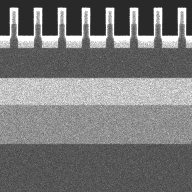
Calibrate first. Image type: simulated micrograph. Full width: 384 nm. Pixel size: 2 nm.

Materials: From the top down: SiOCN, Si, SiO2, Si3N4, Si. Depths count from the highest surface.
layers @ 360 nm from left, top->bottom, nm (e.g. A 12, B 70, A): SiOCN 32, Si 108, SiO2 54, Si3N4 78, Si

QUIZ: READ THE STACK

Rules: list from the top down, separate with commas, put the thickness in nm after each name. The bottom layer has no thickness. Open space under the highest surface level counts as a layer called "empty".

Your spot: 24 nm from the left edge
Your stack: SiOCN 32, Si 108, SiO2 54, Si3N4 78, Si